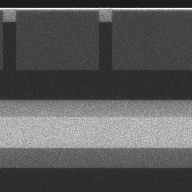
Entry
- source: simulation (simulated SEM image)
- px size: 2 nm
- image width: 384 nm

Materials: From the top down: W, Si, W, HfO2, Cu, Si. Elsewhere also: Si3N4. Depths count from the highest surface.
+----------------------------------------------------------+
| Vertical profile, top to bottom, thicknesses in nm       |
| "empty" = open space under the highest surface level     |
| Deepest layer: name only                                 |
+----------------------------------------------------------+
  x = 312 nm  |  Si3N4 124, Si 60, W 34, HfO2 62, Cu 40, Si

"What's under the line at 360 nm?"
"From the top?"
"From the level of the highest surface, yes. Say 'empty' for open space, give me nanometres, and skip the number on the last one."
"Si3N4 124, Si 60, W 34, HfO2 62, Cu 40, Si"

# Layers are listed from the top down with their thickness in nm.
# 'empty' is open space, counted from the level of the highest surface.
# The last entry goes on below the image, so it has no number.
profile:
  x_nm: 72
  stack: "Si3N4 124, Si 60, W 34, HfO2 62, Cu 40, Si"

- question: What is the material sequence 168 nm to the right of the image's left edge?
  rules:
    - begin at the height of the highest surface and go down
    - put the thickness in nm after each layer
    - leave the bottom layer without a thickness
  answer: Si3N4 124, Si 60, W 34, HfO2 62, Cu 40, Si